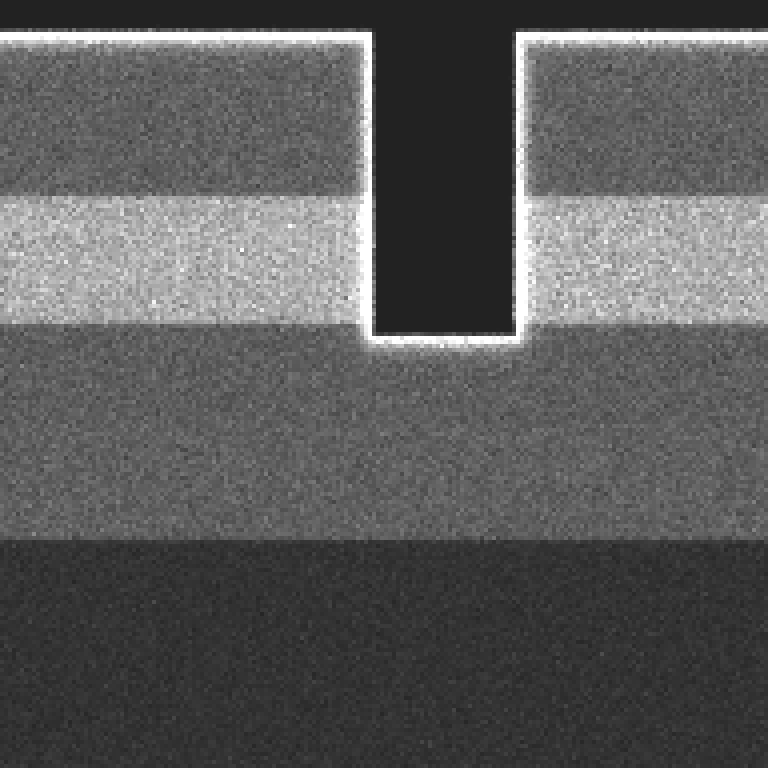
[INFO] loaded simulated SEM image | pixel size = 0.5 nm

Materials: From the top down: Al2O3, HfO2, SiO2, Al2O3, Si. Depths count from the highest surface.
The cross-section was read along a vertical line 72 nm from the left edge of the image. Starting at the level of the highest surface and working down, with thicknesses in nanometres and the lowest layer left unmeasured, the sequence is Al2O3 82, HfO2 64, SiO2 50, Al2O3 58, Si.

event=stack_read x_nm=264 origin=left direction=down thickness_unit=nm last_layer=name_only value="Al2O3 82, HfO2 64, SiO2 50, Al2O3 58, Si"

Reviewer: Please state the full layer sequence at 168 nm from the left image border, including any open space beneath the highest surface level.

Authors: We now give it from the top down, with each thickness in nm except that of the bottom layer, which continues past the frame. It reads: Al2O3 82, HfO2 64, SiO2 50, Al2O3 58, Si